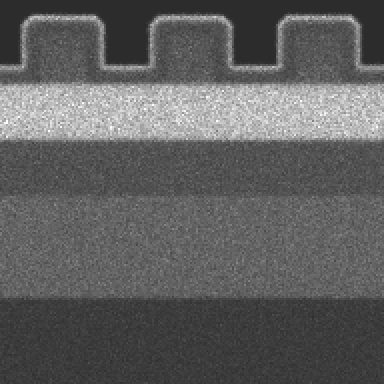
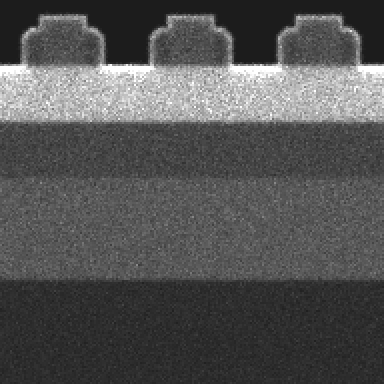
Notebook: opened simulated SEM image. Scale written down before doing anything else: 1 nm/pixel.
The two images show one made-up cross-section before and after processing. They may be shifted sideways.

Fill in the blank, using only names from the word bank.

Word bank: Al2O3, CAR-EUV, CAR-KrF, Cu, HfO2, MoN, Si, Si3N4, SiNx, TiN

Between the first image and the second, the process removed SiNx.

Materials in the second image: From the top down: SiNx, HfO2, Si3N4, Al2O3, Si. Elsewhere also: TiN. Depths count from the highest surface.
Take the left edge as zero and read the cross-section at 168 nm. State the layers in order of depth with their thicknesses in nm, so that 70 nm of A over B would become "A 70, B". TiN 50, HfO2 56, Si3N4 56, Al2O3 102, Si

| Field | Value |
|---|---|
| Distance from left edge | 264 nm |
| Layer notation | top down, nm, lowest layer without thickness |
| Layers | empty 50, HfO2 56, Si3N4 56, Al2O3 102, Si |